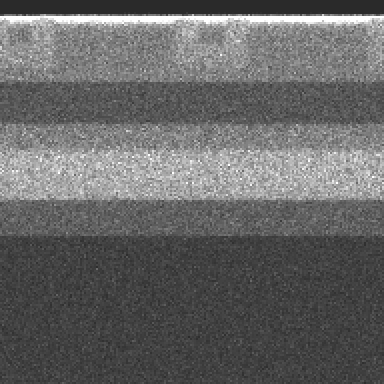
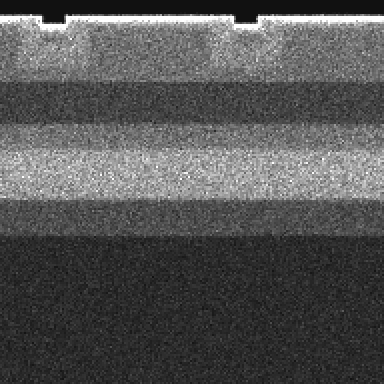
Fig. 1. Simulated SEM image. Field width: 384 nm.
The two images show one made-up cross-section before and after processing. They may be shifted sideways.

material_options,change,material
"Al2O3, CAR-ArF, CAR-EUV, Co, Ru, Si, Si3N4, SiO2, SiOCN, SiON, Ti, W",removed,SiO2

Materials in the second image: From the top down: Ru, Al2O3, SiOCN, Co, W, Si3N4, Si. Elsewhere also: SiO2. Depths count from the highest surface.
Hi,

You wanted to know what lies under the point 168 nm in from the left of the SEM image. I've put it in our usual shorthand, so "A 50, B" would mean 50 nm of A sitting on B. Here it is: Al2O3 66, SiOCN 42, Co 26, W 50, Si3N4 36, Si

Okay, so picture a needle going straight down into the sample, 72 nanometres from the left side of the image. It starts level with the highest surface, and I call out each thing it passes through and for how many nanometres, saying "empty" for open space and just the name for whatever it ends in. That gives Ru 52, Al2O3 14, SiOCN 42, Co 26, W 50, Si3N4 36, Si